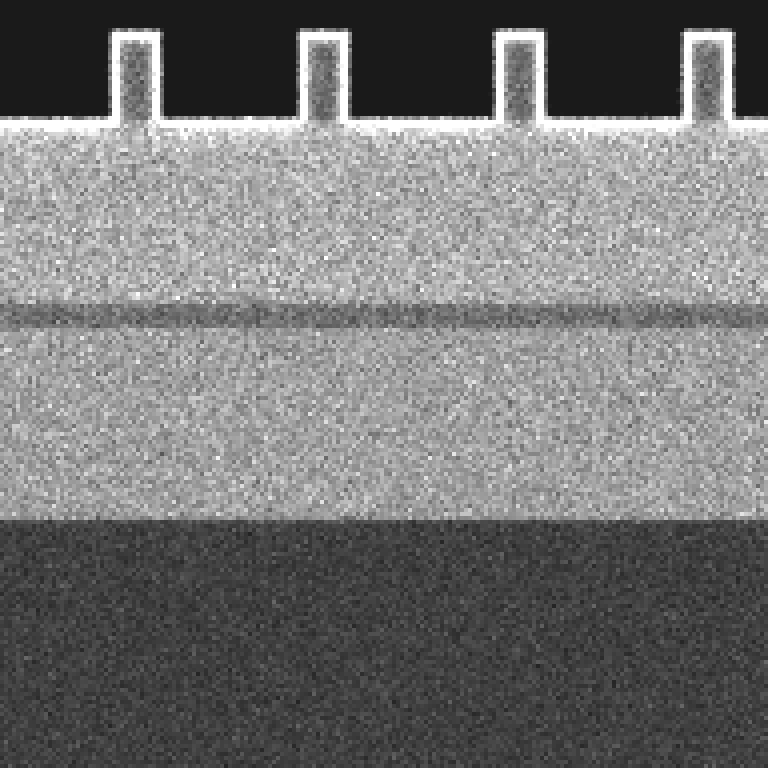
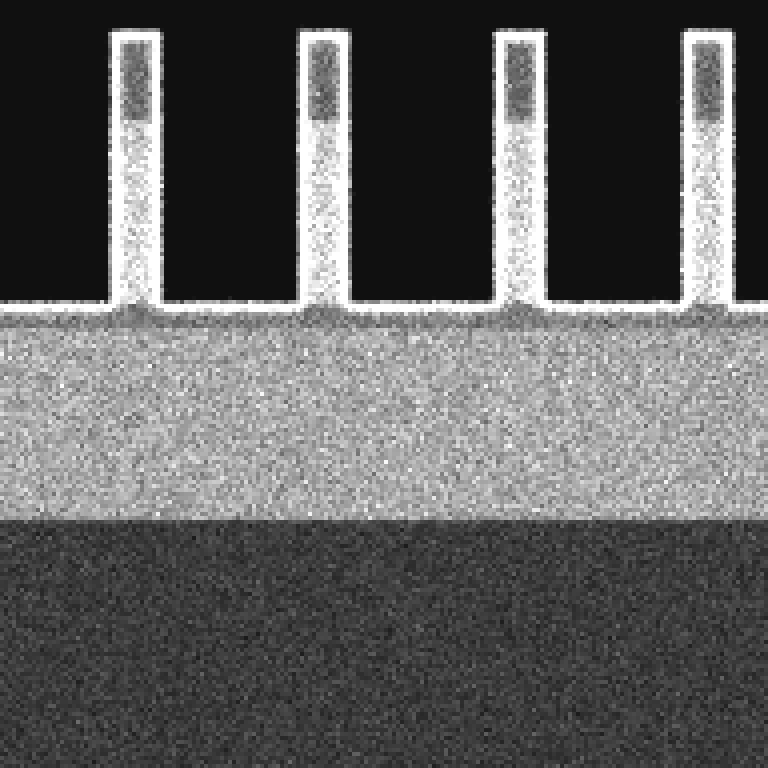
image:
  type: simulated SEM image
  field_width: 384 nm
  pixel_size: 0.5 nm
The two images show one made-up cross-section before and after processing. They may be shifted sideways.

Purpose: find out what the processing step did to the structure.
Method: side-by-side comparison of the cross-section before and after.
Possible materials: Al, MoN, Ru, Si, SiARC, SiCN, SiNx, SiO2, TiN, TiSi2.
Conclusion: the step removed Ru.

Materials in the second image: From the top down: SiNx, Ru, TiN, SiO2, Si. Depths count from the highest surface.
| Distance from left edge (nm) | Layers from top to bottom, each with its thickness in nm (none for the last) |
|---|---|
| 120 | empty 136, TiN 12, SiO2 96, Si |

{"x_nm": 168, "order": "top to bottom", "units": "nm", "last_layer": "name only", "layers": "SiNx 44, Ru 92, TiN 12, SiO2 96, Si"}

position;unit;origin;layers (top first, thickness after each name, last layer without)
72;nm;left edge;SiNx 44, Ru 92, TiN 12, SiO2 96, Si